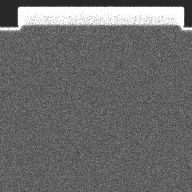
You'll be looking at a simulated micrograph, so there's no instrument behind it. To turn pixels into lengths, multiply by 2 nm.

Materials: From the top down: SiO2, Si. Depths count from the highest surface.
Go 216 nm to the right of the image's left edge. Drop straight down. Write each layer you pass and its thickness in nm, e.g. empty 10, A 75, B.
SiO2 34, Si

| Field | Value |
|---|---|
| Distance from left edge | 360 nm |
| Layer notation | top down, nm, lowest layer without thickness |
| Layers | SiO2 34, Si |